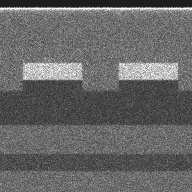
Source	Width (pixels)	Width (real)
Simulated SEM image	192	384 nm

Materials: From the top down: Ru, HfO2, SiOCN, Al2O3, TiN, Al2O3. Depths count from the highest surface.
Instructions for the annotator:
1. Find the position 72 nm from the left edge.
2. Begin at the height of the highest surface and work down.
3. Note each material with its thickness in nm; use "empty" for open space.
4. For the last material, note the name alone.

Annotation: Ru 110, HfO2 34, SiOCN 90, Al2O3 58, TiN 34, Al2O3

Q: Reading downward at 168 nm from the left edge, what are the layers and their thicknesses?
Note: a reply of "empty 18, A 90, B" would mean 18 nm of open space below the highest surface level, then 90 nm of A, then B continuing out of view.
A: Ru 166, SiOCN 68, Al2O3 58, TiN 34, Al2O3